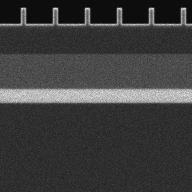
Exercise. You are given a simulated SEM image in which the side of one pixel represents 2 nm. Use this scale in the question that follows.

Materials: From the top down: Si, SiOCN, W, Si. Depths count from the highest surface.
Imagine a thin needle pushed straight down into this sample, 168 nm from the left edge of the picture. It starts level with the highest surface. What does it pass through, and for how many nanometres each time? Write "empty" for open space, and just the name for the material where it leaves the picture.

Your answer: empty 32, Si 60, SiOCN 70, W 28, Si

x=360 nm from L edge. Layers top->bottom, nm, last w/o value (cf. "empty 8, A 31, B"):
empty 32, Si 60, SiOCN 70, W 28, Si